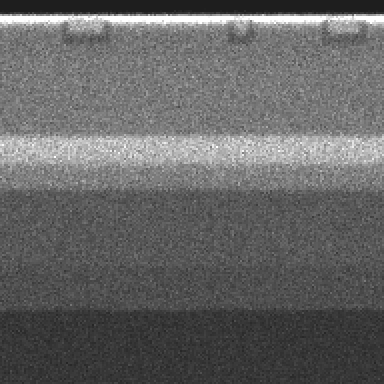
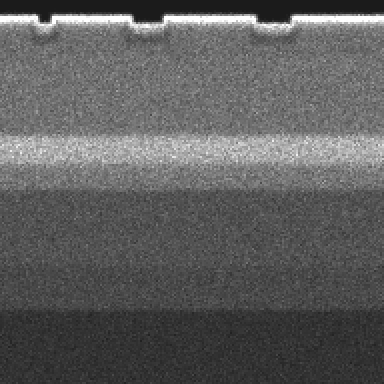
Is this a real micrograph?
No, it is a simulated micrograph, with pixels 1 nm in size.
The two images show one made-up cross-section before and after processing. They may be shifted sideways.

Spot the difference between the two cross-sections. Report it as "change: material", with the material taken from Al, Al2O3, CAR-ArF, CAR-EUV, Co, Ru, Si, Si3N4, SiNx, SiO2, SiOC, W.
removed: Ru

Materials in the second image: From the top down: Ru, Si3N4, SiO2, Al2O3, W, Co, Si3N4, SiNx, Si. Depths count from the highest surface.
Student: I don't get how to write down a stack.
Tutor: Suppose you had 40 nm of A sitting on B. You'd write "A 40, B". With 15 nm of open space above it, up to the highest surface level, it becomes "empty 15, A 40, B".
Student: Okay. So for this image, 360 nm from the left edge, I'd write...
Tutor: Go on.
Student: SiO2 40, Al2O3 80, W 28, Co 26, Si3N4 76, SiNx 44, Si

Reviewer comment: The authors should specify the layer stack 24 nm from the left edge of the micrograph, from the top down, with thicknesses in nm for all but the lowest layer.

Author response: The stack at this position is SiO2 40, Al2O3 80, W 28, Co 26, Si3N4 76, SiNx 44, Si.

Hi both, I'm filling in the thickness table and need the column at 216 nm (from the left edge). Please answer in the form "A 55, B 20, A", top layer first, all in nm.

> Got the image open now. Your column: SiO2 40, Al2O3 80, W 28, Co 26, Si3N4 76, SiNx 44, Si